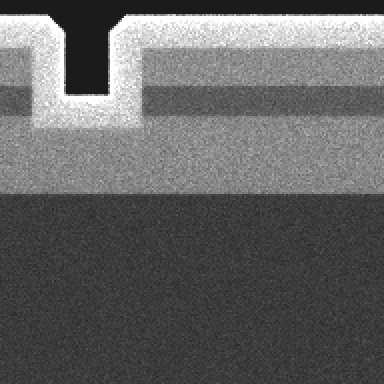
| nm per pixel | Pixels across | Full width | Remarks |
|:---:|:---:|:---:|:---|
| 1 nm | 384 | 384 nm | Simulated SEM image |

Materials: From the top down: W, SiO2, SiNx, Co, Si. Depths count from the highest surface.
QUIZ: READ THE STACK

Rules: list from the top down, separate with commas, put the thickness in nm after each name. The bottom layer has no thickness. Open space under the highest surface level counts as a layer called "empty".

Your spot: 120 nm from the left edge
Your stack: empty 6, W 106, Co 66, Si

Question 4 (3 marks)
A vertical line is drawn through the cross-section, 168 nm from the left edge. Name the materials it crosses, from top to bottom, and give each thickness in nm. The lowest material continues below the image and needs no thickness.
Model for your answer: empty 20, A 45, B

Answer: W 32, SiO2 38, SiNx 30, Co 78, Si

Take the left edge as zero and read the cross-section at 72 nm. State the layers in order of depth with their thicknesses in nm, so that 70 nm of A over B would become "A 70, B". empty 80, W 32, Co 66, Si